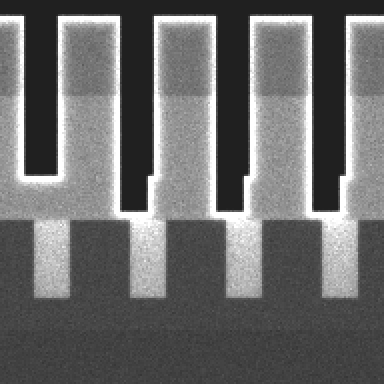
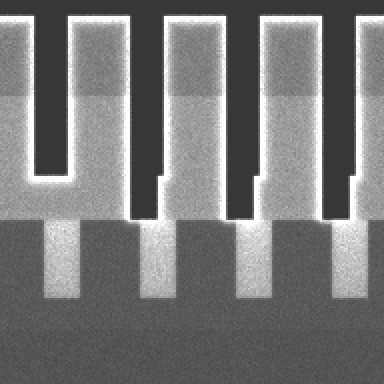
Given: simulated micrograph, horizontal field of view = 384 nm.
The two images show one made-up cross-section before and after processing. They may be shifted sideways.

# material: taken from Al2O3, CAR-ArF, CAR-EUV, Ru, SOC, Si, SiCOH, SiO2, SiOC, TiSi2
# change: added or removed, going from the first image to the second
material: Al2O3
change: removed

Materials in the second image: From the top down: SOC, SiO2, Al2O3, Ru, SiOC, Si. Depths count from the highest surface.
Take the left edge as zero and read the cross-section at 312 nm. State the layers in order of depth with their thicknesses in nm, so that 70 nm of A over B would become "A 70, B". SOC 80, SiO2 116, Al2O3 8, SiOC 110, Si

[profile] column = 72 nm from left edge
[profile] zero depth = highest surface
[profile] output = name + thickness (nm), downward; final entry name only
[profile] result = SOC 80, SiO2 116, Al2O3 8, Ru 78, SiOC 32, Si